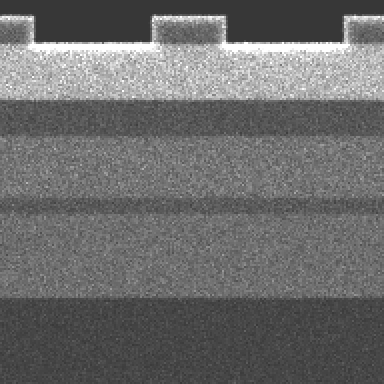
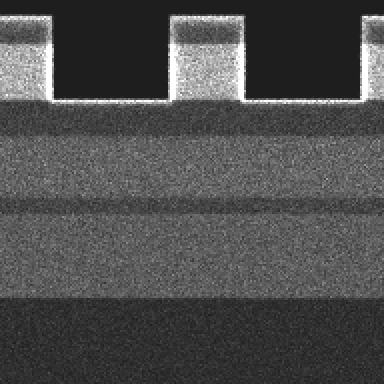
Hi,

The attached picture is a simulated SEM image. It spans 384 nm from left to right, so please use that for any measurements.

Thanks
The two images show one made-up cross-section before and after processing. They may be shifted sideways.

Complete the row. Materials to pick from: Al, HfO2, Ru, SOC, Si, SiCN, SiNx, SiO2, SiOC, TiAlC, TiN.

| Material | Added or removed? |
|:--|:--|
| HfO2 | removed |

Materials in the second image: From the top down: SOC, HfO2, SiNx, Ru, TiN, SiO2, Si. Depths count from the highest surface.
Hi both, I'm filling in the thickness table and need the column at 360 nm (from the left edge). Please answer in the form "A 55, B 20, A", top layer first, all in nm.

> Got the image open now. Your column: empty 84, SiNx 36, Ru 62, TiN 16, SiO2 84, Si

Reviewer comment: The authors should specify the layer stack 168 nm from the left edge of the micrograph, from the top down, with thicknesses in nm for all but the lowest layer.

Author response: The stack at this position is empty 84, SiNx 36, Ru 62, TiN 16, SiO2 84, Si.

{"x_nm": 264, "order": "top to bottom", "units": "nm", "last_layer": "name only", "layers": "empty 84, SiNx 36, Ru 62, TiN 16, SiO2 84, Si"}